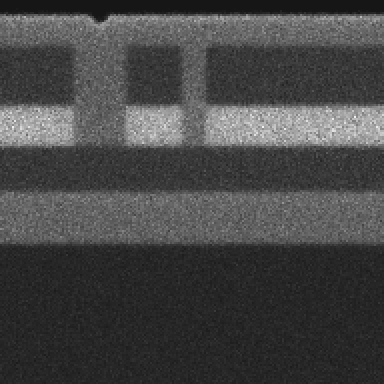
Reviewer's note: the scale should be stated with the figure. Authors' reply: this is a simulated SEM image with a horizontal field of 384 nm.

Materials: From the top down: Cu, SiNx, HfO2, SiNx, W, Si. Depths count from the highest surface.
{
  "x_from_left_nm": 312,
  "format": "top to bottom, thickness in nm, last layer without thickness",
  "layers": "Cu 30, SiNx 60, HfO2 40, SiNx 46, W 52, Si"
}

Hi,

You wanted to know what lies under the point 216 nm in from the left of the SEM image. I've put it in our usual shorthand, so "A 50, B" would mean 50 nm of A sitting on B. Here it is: Cu 30, SiNx 60, HfO2 40, SiNx 46, W 52, Si